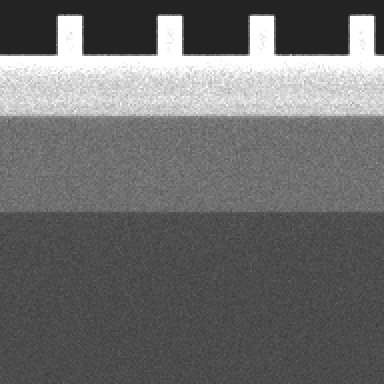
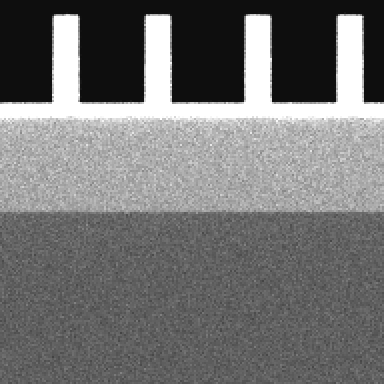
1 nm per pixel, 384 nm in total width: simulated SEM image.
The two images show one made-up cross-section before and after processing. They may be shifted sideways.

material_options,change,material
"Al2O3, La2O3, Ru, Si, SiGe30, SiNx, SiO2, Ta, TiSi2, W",removed,W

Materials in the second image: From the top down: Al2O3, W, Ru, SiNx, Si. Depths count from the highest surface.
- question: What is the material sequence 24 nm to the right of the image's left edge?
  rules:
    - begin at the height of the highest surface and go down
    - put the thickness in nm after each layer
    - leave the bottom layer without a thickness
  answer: empty 88, Ru 12, SiNx 96, Si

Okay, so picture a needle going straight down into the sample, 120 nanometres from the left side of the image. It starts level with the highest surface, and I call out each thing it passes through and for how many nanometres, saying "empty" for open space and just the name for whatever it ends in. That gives empty 88, Ru 12, SiNx 96, Si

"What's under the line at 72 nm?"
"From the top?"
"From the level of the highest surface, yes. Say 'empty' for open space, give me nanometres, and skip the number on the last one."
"Al2O3 40, W 48, Ru 12, SiNx 96, Si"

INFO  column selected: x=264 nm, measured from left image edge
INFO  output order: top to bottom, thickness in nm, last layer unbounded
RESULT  Al2O3 40, W 48, Ru 12, SiNx 96, Si